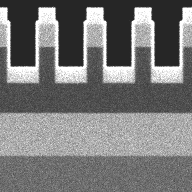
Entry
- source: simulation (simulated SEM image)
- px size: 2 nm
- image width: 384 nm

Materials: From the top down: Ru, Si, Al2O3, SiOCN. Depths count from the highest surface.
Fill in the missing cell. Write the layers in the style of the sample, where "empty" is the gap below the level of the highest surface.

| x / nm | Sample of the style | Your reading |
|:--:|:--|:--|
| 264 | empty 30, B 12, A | empty 28, Ru 122, Si 60, Al2O3 86, SiOCN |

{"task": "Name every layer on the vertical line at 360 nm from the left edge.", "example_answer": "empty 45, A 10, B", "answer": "empty 28, Ru 122, Si 60, Al2O3 86, SiOCN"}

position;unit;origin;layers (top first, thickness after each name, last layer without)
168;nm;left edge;empty 28, Ru 122, Si 60, Al2O3 86, SiOCN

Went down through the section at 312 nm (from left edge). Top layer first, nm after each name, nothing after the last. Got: empty 118, Ru 32, Si 60, Al2O3 86, SiOCN